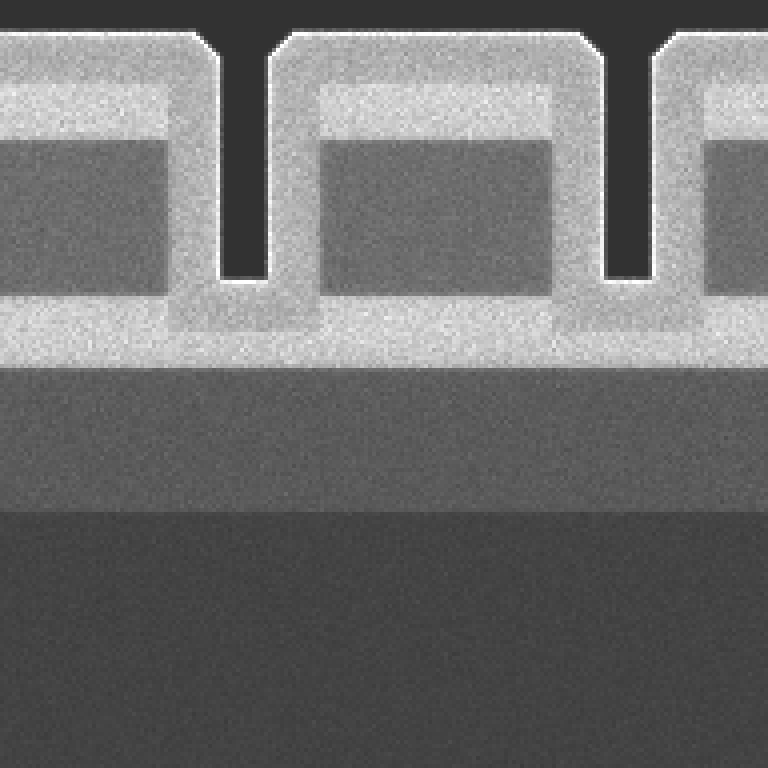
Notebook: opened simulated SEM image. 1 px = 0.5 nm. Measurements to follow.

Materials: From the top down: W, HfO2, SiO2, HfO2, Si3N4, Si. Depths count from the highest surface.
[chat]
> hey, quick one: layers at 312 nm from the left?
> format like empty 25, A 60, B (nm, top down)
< empty 124, W 26, HfO2 18, Si3N4 72, Si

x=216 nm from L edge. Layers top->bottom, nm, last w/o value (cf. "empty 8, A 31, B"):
W 26, HfO2 28, SiO2 78, HfO2 36, Si3N4 72, Si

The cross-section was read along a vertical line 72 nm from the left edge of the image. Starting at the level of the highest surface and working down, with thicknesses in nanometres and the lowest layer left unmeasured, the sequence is W 26, HfO2 28, SiO2 78, HfO2 36, Si3N4 72, Si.